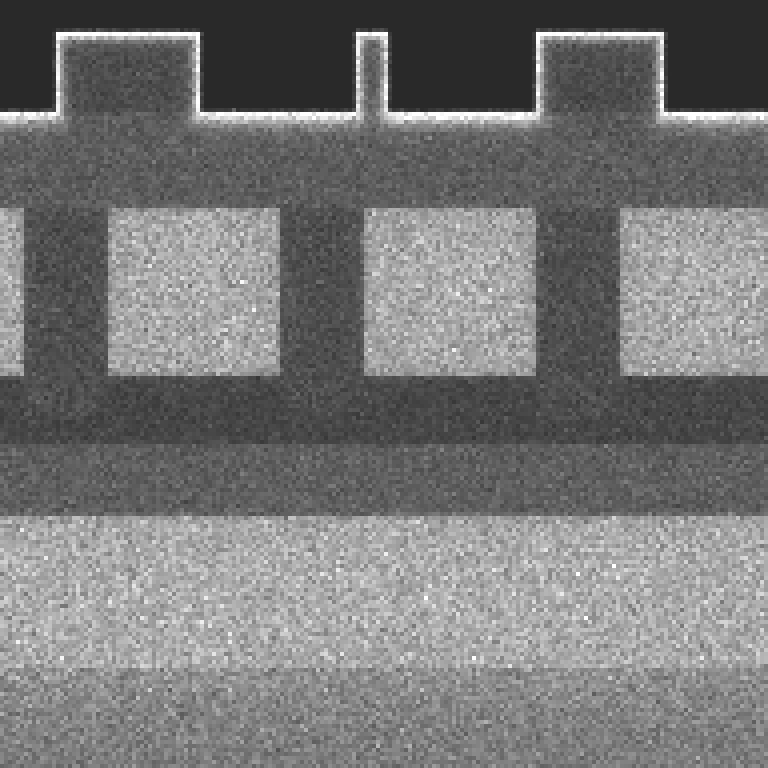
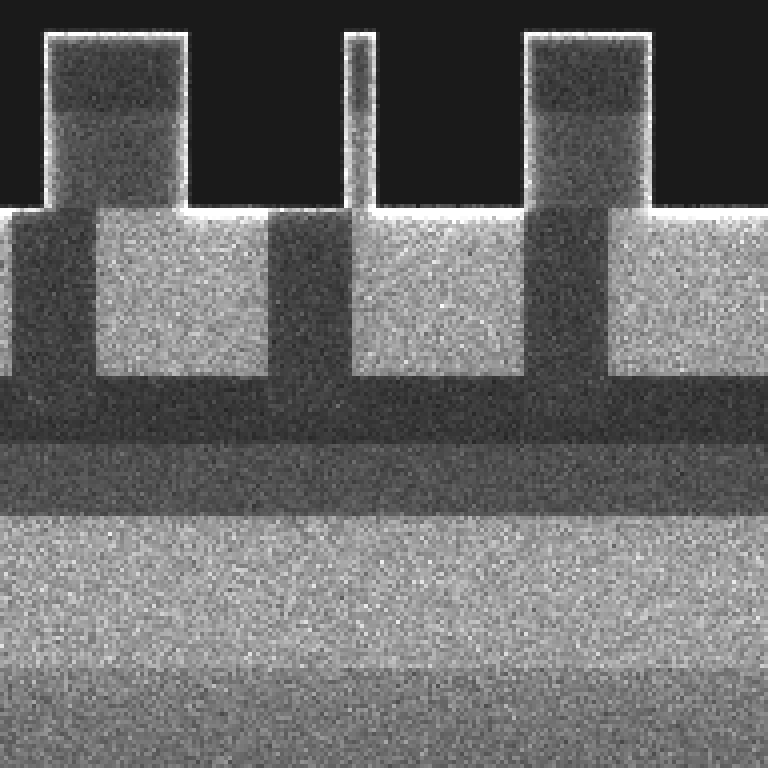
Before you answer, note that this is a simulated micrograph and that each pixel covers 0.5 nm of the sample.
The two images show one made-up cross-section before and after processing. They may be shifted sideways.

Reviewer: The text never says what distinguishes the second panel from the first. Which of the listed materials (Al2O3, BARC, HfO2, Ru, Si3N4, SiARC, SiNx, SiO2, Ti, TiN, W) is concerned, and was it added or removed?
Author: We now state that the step removed SiO2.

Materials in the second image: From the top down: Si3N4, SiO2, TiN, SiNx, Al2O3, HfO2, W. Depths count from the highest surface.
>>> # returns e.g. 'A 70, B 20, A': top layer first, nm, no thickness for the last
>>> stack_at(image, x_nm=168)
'empty 88, TiN 104, SiNx 14, Al2O3 36, HfO2 76, W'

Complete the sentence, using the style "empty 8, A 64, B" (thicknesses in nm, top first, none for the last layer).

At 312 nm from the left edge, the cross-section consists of Si3N4 40, SiO2 48, HfO2 84, SiNx 34, Al2O3 36, HfO2 76, W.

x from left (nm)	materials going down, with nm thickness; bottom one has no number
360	empty 88, HfO2 84, SiNx 34, Al2O3 36, HfO2 76, W